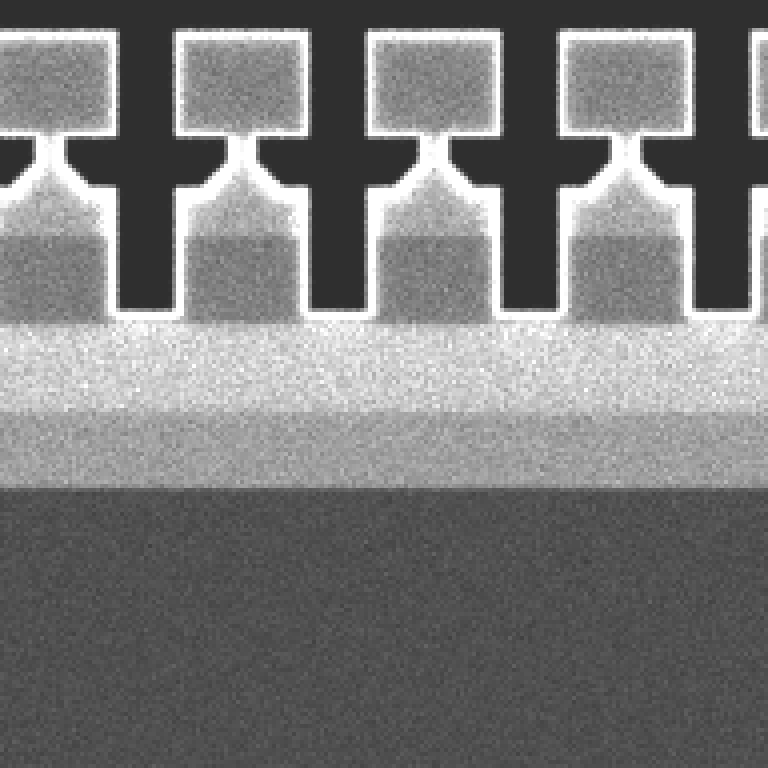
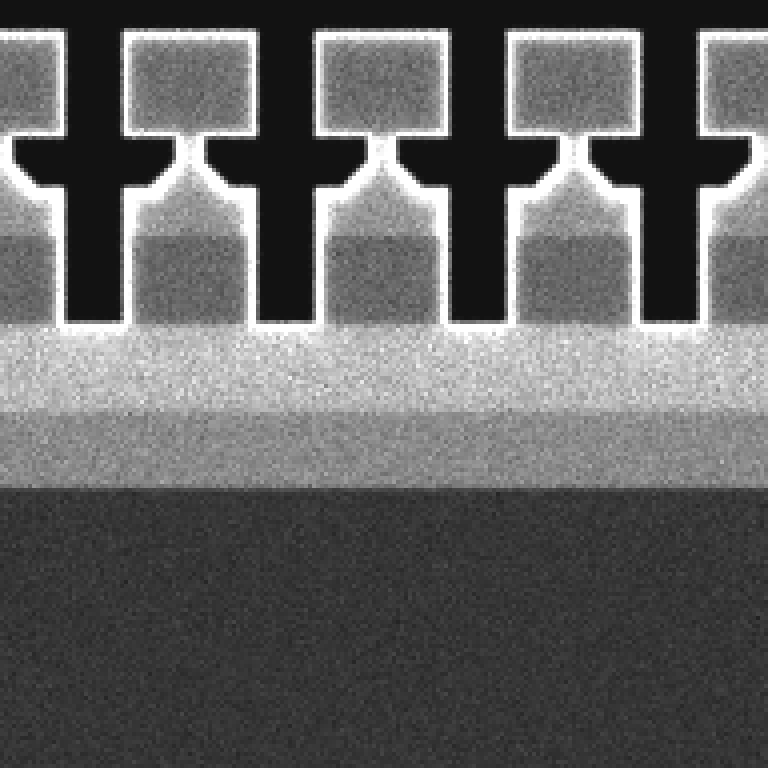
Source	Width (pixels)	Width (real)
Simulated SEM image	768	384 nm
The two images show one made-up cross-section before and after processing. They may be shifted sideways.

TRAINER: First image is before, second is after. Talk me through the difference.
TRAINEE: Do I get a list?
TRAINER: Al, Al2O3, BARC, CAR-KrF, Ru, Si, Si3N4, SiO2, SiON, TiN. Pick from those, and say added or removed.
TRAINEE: removed: Si3N4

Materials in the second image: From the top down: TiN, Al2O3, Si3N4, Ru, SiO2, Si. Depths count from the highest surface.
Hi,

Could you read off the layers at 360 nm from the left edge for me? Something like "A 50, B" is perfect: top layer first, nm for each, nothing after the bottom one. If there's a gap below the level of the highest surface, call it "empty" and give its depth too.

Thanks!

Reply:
TiN 52, empty 26, Al2O3 24, Si3N4 44, Ru 44, SiO2 38, Si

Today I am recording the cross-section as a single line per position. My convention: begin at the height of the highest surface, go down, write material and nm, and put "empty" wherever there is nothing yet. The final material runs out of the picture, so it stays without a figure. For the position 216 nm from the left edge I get TiN 52, empty 26, Al2O3 24, Si3N4 44, Ru 44, SiO2 38, Si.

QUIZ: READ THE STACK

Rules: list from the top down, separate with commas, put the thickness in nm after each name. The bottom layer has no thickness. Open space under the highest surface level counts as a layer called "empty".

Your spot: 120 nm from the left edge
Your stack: TiN 52, empty 26, Al2O3 24, Si3N4 44, Ru 44, SiO2 38, Si